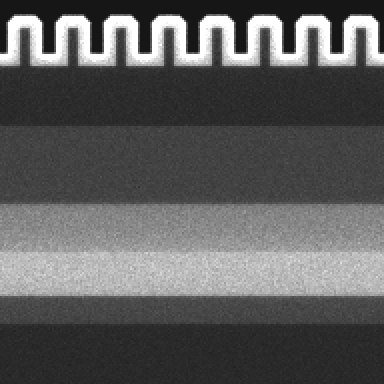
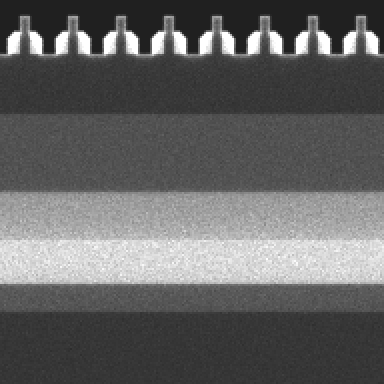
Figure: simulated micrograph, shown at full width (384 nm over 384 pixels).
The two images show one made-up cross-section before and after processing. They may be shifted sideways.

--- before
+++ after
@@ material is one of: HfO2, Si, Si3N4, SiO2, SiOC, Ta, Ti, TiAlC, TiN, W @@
HfO2 removed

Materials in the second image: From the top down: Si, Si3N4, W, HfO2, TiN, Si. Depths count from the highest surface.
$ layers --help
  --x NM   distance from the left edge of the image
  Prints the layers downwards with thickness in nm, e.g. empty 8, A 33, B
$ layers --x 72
Si 98, Si3N4 78, W 48, HfO2 44, TiN 28, Si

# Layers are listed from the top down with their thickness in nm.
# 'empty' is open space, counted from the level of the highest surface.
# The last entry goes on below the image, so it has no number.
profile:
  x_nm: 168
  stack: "Si 98, Si3N4 78, W 48, HfO2 44, TiN 28, Si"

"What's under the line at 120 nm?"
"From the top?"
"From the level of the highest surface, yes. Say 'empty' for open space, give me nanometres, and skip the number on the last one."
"Si 98, Si3N4 78, W 48, HfO2 44, TiN 28, Si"